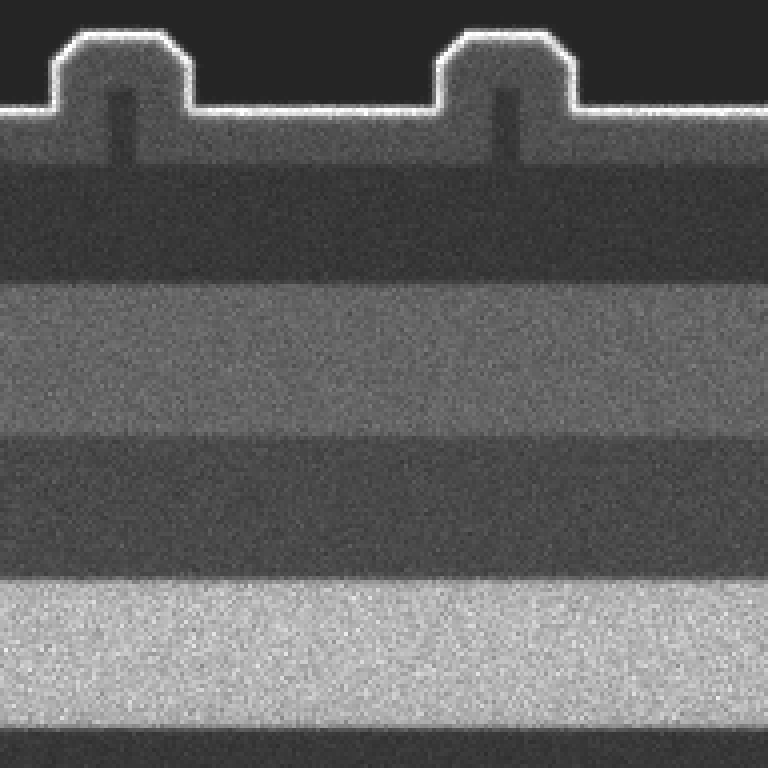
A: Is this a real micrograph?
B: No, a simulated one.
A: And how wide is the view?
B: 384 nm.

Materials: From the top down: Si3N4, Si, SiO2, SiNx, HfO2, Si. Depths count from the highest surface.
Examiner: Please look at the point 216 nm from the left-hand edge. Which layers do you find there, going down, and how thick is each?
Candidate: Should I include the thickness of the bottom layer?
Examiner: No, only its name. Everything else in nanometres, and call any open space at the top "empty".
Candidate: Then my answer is empty 38, Si3N4 28, Si 60, SiO2 76, SiNx 72, HfO2 74, Si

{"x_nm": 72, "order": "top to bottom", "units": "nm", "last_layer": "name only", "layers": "Si3N4 66, Si 60, SiO2 76, SiNx 72, HfO2 74, Si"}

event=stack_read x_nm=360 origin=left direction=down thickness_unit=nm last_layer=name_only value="empty 38, Si3N4 28, Si 60, SiO2 76, SiNx 72, HfO2 74, Si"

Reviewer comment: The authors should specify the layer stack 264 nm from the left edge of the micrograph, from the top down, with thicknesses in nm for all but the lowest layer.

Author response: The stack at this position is Si3N4 66, Si 60, SiO2 76, SiNx 72, HfO2 74, Si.